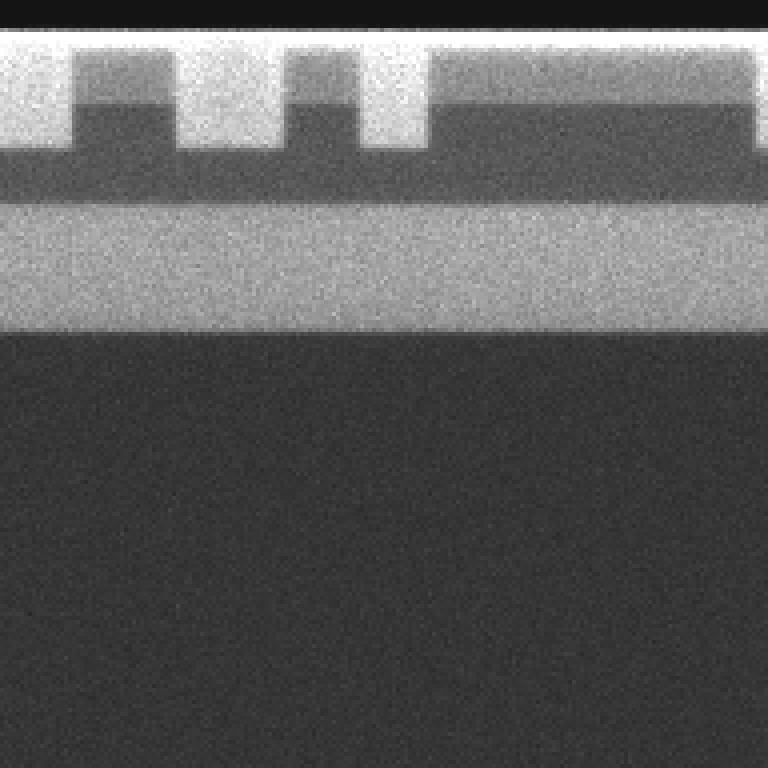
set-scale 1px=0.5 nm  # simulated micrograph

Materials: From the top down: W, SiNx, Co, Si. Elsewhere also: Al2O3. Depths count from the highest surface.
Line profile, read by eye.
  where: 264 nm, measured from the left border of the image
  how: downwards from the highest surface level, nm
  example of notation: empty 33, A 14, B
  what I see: Al2O3 36, SiNx 50, Co 64, Si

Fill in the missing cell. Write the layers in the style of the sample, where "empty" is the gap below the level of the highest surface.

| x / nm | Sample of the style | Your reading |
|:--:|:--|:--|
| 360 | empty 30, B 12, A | Al2O3 36, SiNx 50, Co 64, Si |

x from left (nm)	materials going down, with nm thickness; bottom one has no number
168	Al2O3 36, SiNx 50, Co 64, Si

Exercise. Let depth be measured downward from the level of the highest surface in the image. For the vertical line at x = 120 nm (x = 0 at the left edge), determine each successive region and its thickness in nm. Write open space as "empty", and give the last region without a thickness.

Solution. W 58, SiNx 28, Co 64, Si